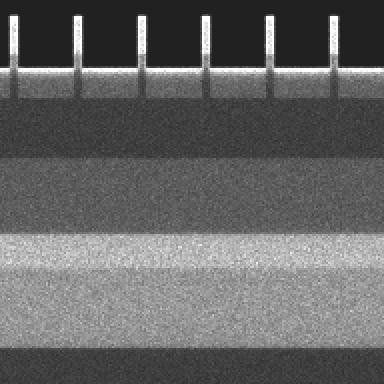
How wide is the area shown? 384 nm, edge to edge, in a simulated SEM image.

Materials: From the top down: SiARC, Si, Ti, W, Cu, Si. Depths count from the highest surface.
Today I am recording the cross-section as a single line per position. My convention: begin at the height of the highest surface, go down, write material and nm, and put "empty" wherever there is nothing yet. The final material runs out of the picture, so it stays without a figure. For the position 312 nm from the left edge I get empty 52, SiARC 30, Si 60, Ti 76, W 34, Cu 80, Si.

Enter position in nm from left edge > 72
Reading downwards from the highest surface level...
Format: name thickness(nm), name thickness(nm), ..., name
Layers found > empty 52, SiARC 30, Si 60, Ti 76, W 34, Cu 80, Si